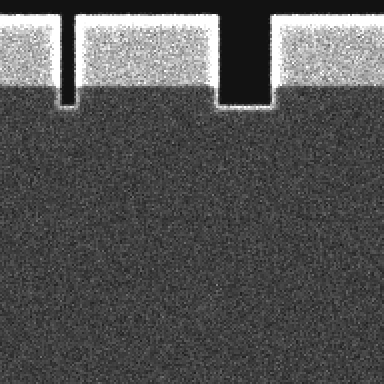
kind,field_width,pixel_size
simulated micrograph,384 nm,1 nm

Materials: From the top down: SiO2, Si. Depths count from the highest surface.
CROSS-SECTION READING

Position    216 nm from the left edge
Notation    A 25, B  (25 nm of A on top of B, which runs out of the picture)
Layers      SiO2 70, Si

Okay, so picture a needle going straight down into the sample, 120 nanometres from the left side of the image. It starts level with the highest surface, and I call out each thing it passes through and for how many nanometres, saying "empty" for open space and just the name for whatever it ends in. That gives SiO2 70, Si